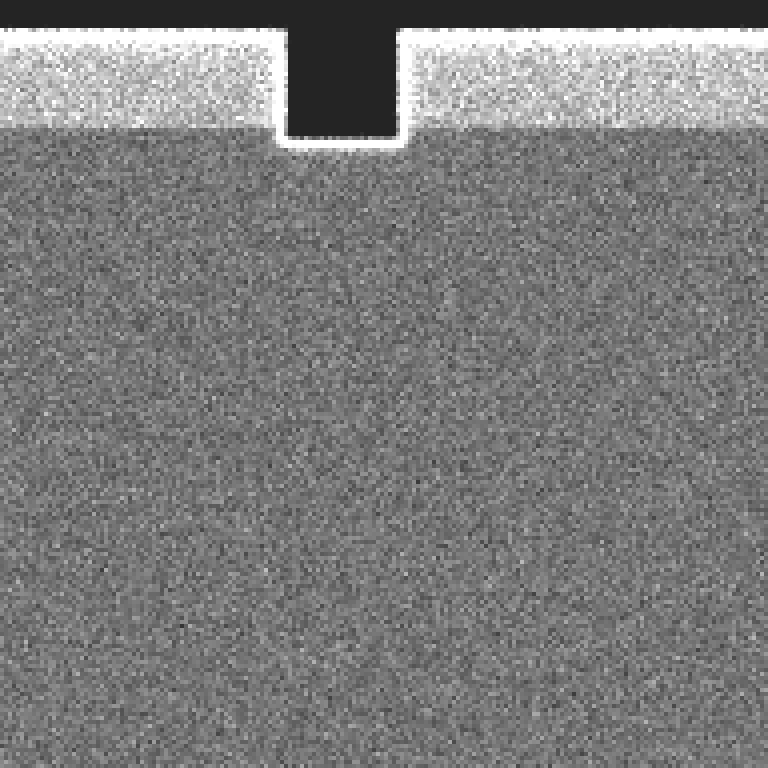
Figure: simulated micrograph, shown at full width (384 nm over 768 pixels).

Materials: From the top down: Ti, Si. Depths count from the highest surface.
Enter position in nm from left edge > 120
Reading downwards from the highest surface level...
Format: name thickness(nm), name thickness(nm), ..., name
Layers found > Ti 48, Si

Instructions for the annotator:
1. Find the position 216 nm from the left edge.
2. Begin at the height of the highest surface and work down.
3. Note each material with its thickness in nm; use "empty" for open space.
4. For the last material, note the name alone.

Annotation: Ti 48, Si